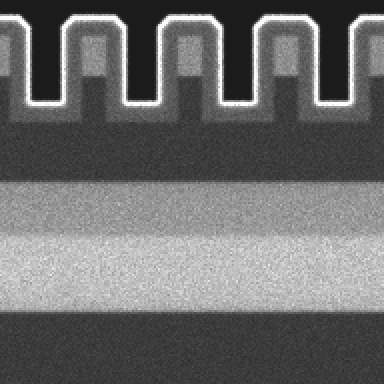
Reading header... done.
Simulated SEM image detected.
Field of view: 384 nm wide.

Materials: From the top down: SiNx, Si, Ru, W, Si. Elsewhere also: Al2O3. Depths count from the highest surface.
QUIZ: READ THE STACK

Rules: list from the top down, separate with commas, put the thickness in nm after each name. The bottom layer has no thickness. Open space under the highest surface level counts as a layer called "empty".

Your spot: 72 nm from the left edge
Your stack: SiNx 106, Si 60, Ru 54, W 76, Si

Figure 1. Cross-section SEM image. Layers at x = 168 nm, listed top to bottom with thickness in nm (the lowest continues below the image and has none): SiNx 106, Si 60, Ru 54, W 76, Si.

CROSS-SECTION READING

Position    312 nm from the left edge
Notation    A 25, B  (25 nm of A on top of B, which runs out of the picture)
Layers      empty 6, SiNx 100, Si 60, Ru 54, W 76, Si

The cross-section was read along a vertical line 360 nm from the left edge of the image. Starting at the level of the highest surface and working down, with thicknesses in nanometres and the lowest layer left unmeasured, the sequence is SiNx 106, Si 60, Ru 54, W 76, Si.